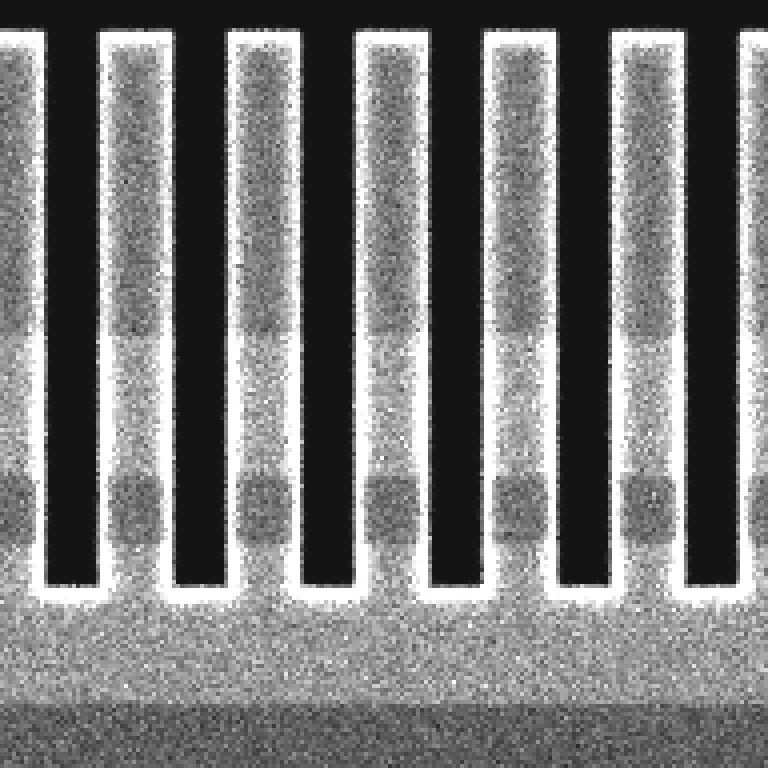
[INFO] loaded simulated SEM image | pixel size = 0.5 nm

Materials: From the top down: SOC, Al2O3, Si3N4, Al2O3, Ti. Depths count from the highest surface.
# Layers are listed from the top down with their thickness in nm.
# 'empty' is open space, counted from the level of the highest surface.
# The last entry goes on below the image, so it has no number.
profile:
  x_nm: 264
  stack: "SOC 152, Al2O3 70, Si3N4 34, Al2O3 80, Ti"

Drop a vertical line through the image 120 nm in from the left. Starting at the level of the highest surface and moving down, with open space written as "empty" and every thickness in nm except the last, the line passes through SOC 152, Al2O3 70, Si3N4 34, Al2O3 80, Ti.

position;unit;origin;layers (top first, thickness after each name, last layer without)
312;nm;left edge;SOC 152, Al2O3 70, Si3N4 34, Al2O3 80, Ti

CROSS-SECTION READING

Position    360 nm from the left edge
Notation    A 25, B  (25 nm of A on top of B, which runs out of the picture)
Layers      empty 278, Al2O3 58, Ti